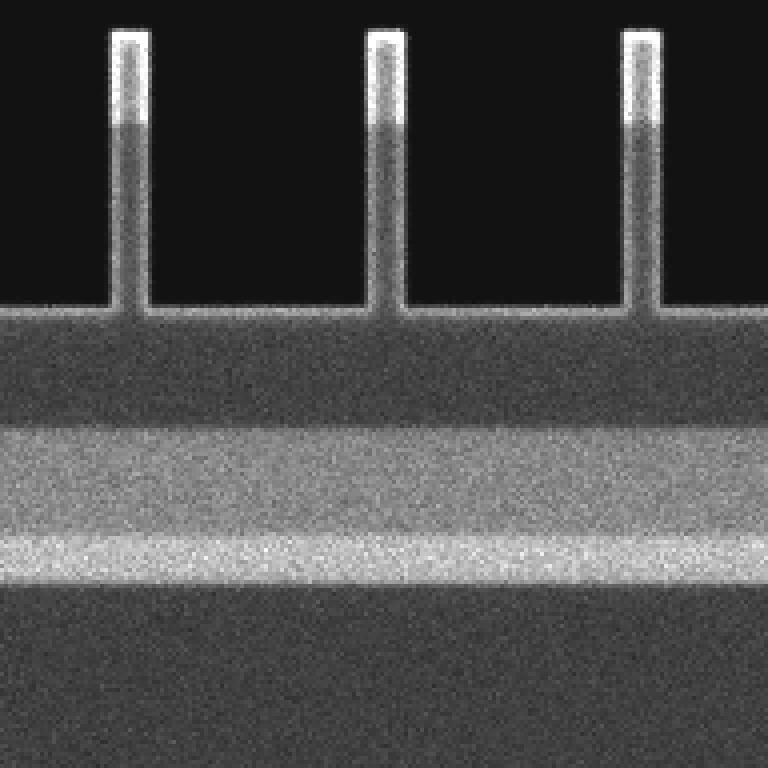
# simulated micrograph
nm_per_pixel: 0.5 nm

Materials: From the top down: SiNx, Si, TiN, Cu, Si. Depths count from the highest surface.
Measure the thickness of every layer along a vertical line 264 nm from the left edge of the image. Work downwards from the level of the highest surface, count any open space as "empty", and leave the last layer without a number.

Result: empty 138, Si 60, TiN 54, Cu 24, Si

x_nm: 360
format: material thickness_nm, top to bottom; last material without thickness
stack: empty 138, Si 60, TiN 54, Cu 24, Si